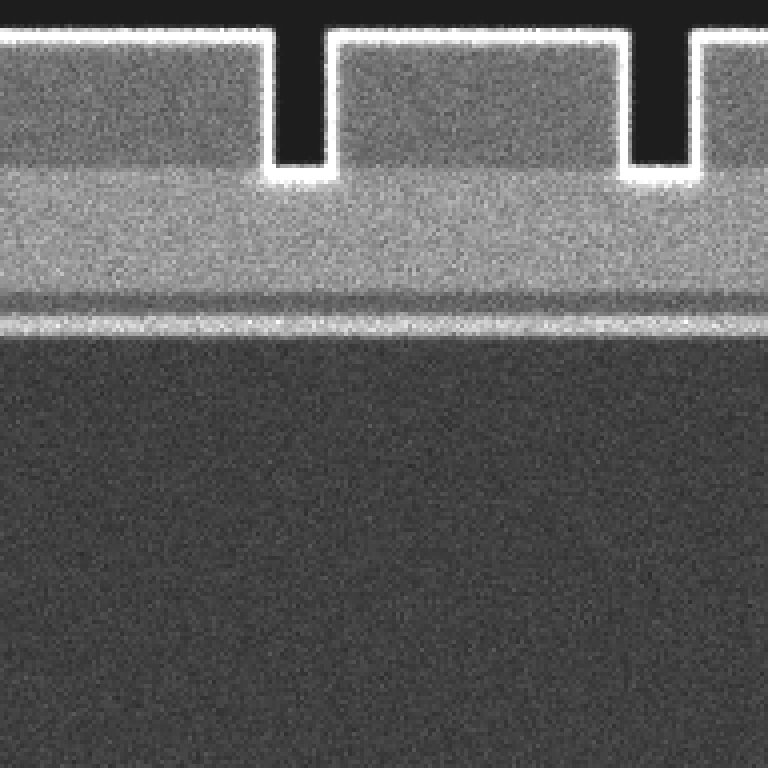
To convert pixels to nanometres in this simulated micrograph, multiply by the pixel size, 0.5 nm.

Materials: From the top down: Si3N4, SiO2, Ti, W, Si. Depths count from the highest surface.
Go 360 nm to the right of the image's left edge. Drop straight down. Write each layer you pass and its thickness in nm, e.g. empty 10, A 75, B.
Si3N4 68, SiO2 62, Ti 12, W 10, Si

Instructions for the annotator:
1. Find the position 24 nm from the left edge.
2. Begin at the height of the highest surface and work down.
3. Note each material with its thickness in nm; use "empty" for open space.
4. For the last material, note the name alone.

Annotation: Si3N4 68, SiO2 62, Ti 12, W 10, Si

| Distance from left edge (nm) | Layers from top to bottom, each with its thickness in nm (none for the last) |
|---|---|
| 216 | Si3N4 68, SiO2 62, Ti 12, W 10, Si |